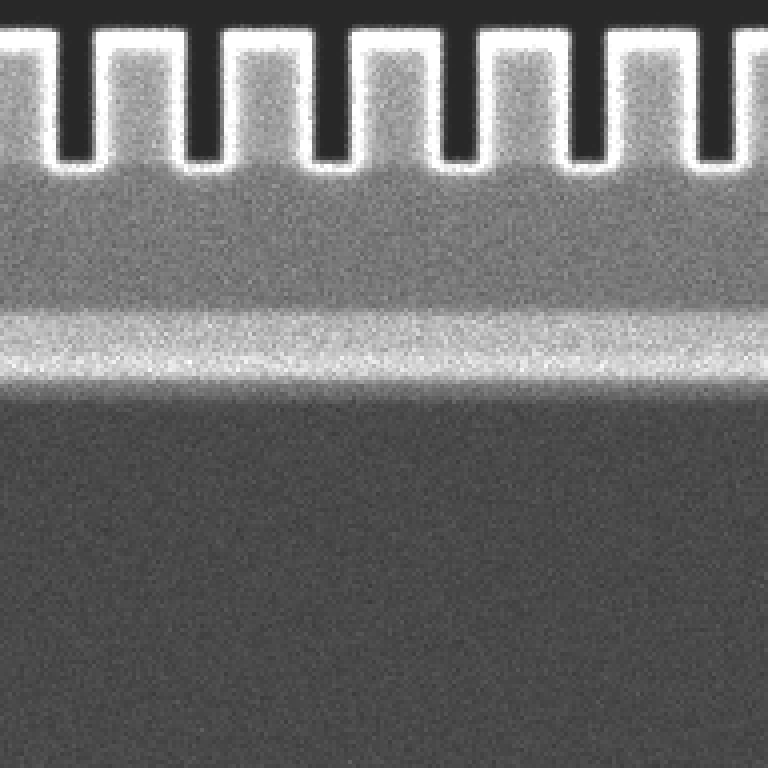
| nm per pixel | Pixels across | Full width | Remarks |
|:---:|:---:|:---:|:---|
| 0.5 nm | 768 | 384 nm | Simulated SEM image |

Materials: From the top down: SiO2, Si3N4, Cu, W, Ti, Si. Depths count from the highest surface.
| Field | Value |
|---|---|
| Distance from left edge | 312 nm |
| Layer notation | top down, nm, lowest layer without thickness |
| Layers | SiO2 66, Si3N4 74, Cu 22, W 12, Ti 10, Si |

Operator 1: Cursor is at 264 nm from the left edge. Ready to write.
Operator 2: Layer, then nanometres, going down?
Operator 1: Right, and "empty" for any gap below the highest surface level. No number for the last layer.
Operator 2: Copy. SiO2 66, Si3N4 74, Cu 22, W 12, Ti 10, Si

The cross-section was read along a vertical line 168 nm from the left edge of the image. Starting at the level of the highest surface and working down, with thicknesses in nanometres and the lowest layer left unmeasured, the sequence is empty 66, Si3N4 74, Cu 22, W 12, Ti 10, Si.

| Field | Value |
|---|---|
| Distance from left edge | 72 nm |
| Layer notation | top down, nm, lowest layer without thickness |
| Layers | SiO2 66, Si3N4 74, Cu 22, W 12, Ti 10, Si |